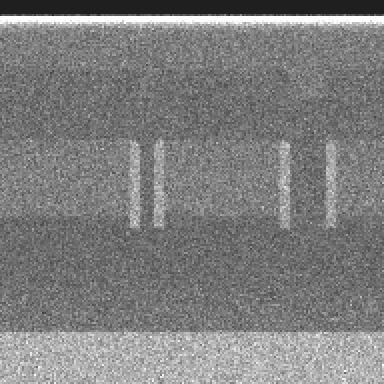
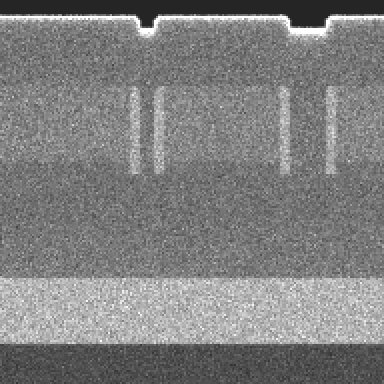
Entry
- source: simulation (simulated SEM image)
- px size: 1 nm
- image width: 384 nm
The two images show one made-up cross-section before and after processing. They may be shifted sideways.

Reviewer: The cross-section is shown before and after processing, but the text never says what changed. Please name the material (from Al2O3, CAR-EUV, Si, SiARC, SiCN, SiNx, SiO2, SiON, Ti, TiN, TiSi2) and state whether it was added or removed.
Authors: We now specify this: SiARC, removed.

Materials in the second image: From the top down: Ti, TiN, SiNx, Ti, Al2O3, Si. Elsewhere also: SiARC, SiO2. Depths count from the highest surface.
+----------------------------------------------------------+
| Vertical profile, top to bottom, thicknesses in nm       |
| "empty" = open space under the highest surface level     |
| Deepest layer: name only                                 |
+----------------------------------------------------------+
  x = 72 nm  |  Ti 70, TiN 76, SiNx 68, Ti 48, Al2O3 66, Si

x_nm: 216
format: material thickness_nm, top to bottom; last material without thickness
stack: Ti 70, TiN 76, SiNx 68, Ti 48, Al2O3 66, Si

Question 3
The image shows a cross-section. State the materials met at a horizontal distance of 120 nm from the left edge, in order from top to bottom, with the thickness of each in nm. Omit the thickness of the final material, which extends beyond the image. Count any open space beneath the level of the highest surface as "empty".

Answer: Ti 70, TiN 76, SiNx 68, Ti 48, Al2O3 66, Si